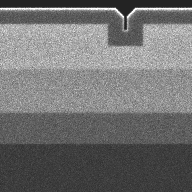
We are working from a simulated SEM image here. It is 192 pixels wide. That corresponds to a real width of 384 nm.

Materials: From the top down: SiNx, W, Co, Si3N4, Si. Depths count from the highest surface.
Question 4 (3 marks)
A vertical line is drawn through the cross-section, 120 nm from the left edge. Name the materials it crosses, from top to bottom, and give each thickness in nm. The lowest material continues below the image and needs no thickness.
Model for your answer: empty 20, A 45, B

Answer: SiNx 32, W 90, Co 88, Si3N4 62, Si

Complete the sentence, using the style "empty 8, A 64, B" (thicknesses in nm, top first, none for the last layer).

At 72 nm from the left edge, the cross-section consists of SiNx 32, W 90, Co 88, Si3N4 62, Si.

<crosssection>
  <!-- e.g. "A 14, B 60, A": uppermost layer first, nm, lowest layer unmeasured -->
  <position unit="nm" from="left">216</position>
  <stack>SiNx 76, W 46, Co 88, Si3N4 62, Si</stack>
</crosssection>